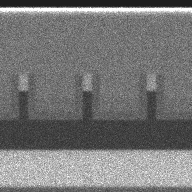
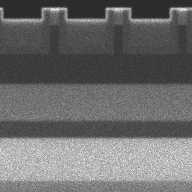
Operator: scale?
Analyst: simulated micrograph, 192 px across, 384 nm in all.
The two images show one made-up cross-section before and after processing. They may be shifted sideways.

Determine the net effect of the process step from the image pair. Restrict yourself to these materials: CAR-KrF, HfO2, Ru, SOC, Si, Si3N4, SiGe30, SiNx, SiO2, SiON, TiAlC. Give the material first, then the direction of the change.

SOC: removed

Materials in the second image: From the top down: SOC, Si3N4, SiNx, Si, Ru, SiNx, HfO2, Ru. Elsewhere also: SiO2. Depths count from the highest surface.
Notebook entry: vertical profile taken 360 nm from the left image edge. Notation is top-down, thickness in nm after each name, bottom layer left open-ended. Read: SiO2 34, Si 118, Ru 74, SiNx 34, HfO2 86, Ru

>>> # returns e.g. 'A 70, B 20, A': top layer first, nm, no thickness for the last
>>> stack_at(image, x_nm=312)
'empty 22, SOC 24, Si3N4 30, SiNx 16, Si 60, Ru 74, SiNx 34, HfO2 86, Ru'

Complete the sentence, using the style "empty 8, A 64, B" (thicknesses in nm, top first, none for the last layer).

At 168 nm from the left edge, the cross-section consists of empty 22, SOC 24, Si3N4 30, SiNx 16, Si 60, Ru 74, SiNx 34, HfO2 86, Ru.